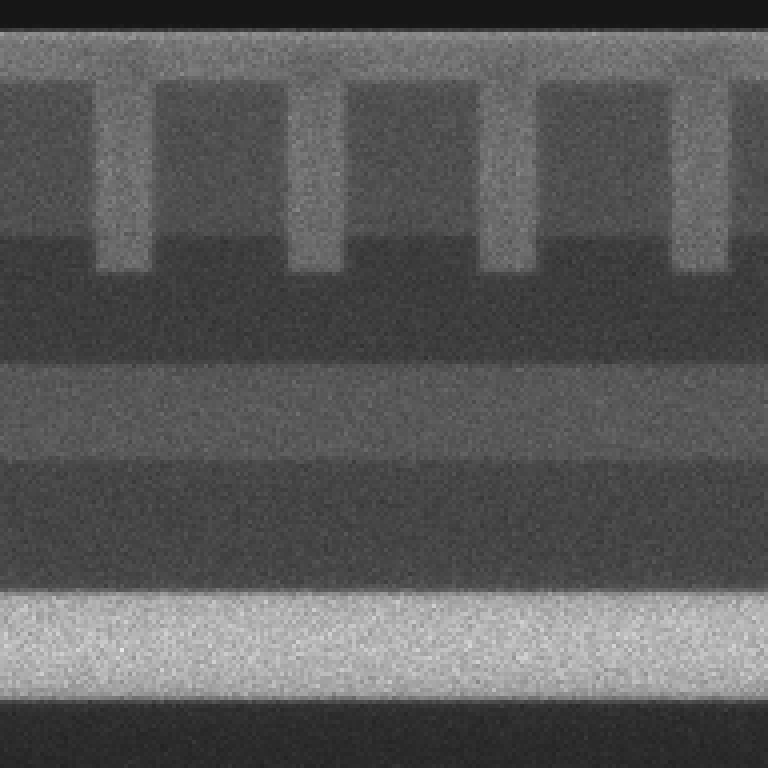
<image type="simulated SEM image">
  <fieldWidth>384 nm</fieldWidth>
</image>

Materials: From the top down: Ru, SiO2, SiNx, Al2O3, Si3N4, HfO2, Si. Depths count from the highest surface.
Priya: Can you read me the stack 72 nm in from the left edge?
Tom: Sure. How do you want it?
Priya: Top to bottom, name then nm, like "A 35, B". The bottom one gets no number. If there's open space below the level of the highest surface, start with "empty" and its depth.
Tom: Ru 120, SiNx 46, Al2O3 48, Si3N4 66, HfO2 54, Si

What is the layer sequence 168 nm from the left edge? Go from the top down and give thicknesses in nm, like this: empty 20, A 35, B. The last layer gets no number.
Ru 120, SiNx 46, Al2O3 48, Si3N4 66, HfO2 54, Si